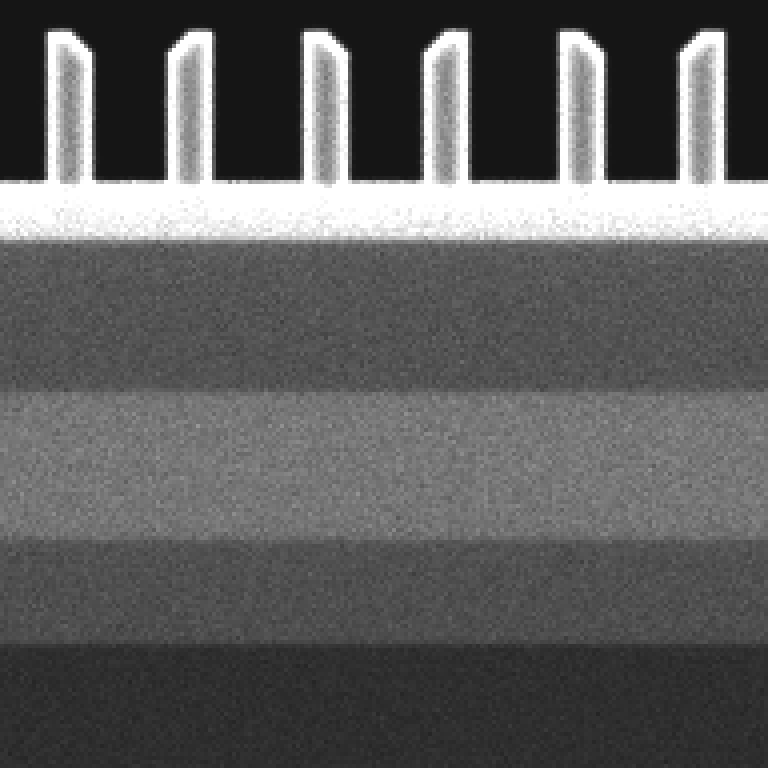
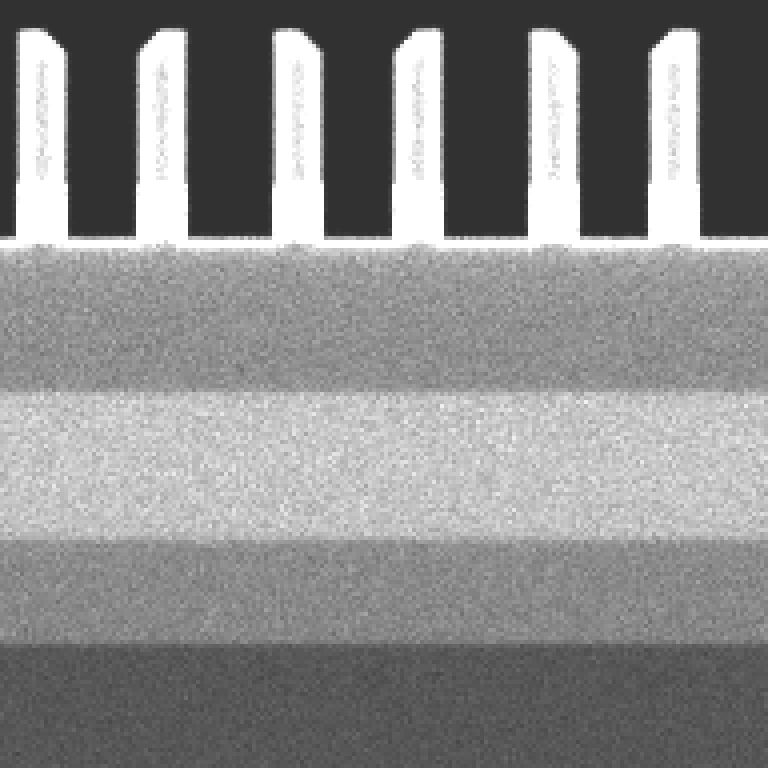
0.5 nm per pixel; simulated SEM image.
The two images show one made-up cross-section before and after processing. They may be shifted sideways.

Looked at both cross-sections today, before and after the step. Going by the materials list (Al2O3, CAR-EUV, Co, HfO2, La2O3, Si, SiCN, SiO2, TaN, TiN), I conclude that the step removed HfO2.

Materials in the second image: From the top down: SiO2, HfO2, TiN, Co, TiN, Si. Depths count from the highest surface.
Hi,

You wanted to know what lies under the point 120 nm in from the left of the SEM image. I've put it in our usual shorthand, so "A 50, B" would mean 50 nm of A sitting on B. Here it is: empty 104, TiN 76, Co 74, TiN 52, Si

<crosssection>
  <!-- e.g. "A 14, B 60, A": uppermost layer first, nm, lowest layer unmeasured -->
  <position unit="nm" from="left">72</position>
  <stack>empty 8, SiO2 68, HfO2 28, TiN 76, Co 74, TiN 52, Si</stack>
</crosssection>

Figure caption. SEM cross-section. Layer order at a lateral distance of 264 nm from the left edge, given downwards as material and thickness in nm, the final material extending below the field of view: empty 104, TiN 76, Co 74, TiN 52, Si